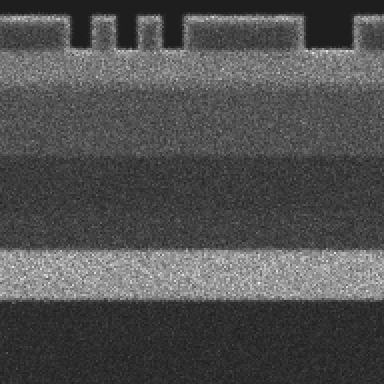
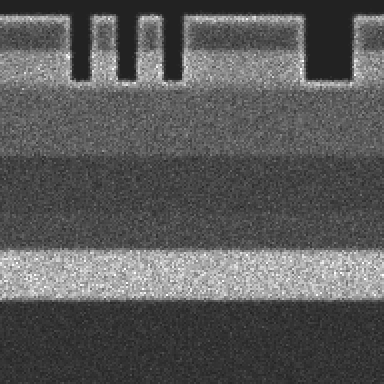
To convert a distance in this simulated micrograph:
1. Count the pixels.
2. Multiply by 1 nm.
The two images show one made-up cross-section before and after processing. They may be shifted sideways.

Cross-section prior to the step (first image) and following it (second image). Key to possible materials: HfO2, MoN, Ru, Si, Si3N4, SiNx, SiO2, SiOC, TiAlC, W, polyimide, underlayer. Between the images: W was removed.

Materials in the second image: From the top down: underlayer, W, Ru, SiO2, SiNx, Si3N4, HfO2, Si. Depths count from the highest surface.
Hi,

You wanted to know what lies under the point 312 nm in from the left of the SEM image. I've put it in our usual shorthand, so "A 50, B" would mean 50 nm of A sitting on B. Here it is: empty 66, Ru 8, SiO2 66, SiNx 56, Si3N4 38, HfO2 50, Si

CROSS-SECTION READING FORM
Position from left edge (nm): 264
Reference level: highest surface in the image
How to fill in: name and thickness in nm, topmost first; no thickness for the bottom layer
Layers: underlayer 34, W 32, Ru 8, SiO2 66, SiNx 56, Si3N4 38, HfO2 50, Si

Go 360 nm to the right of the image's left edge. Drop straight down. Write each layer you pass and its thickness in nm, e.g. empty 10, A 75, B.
underlayer 34, W 32, Ru 8, SiO2 66, SiNx 56, Si3N4 38, HfO2 50, Si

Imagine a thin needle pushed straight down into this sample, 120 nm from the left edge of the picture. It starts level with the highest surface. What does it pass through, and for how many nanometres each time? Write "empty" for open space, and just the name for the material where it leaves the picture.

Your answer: empty 66, Ru 8, SiO2 66, SiNx 56, Si3N4 38, HfO2 50, Si